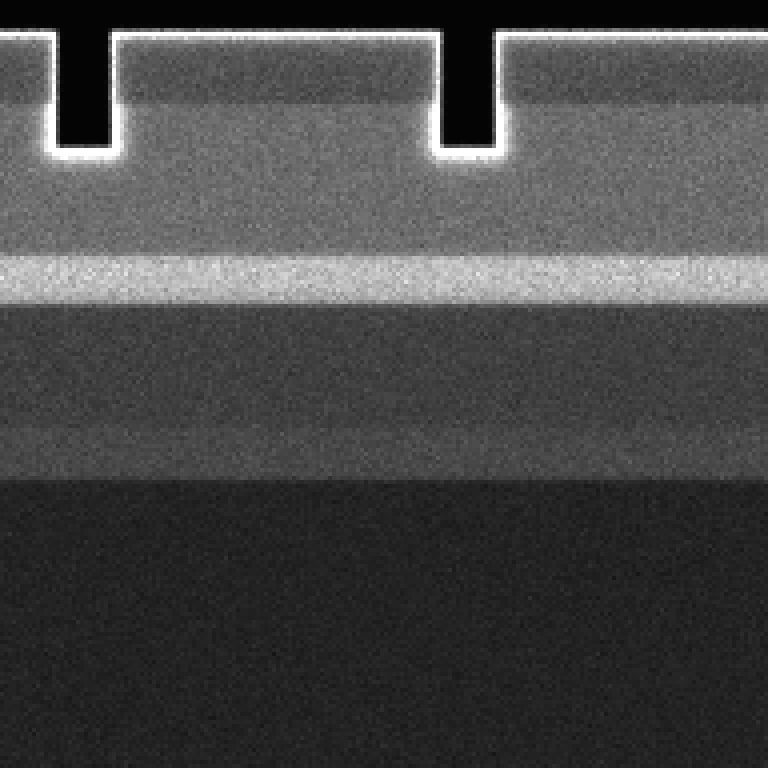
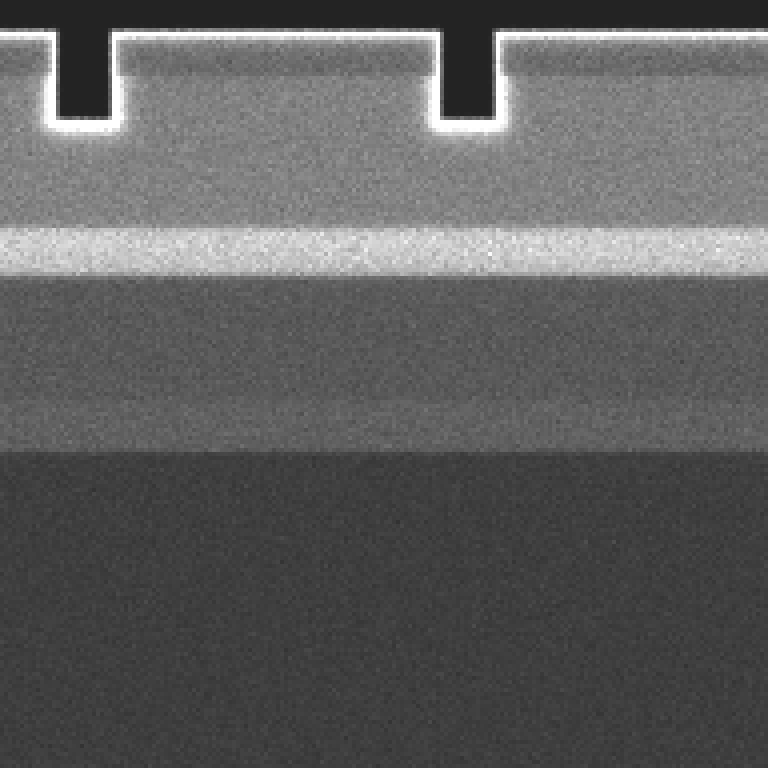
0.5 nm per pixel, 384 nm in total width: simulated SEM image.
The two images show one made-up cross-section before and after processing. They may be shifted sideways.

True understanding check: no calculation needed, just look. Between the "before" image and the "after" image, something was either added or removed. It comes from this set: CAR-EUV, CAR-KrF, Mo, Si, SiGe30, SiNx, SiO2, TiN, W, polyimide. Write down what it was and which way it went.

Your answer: TiN (removed)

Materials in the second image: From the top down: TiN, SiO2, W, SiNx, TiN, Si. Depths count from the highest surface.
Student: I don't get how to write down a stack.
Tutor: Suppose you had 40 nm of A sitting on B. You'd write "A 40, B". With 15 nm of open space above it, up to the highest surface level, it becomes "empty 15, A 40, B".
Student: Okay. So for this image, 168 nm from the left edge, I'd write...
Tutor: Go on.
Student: TiN 22, SiO2 76, W 24, SiNx 62, TiN 26, Si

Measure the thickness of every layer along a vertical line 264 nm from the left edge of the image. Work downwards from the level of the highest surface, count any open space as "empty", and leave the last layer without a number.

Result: TiN 22, SiO2 76, W 24, SiNx 62, TiN 26, Si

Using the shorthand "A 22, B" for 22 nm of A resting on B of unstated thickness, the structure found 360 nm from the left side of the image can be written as TiN 22, SiO2 76, W 24, SiNx 62, TiN 26, Si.